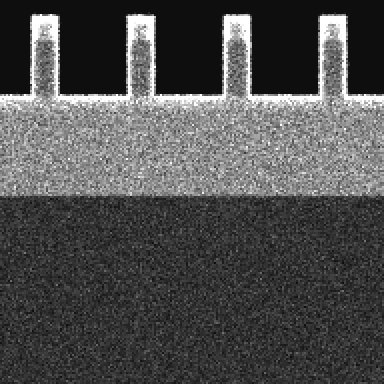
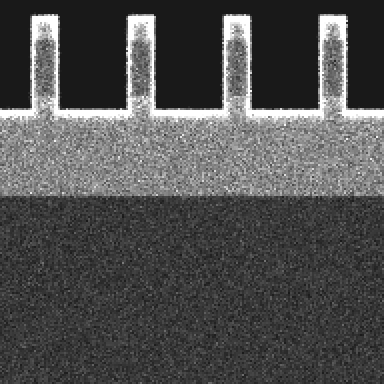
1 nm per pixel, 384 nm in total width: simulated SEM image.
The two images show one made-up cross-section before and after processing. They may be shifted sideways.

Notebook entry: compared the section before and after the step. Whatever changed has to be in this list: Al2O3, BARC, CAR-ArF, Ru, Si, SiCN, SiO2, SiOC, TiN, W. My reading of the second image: Ru removed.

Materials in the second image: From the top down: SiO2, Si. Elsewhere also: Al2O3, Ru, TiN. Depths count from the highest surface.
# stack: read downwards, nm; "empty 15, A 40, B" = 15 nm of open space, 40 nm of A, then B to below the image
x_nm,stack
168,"empty 94, SiO2 86, Si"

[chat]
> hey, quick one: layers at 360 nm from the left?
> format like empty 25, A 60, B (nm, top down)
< empty 94, SiO2 86, Si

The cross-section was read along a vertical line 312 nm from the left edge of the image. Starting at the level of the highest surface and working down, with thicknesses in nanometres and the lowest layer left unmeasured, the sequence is empty 94, SiO2 86, Si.